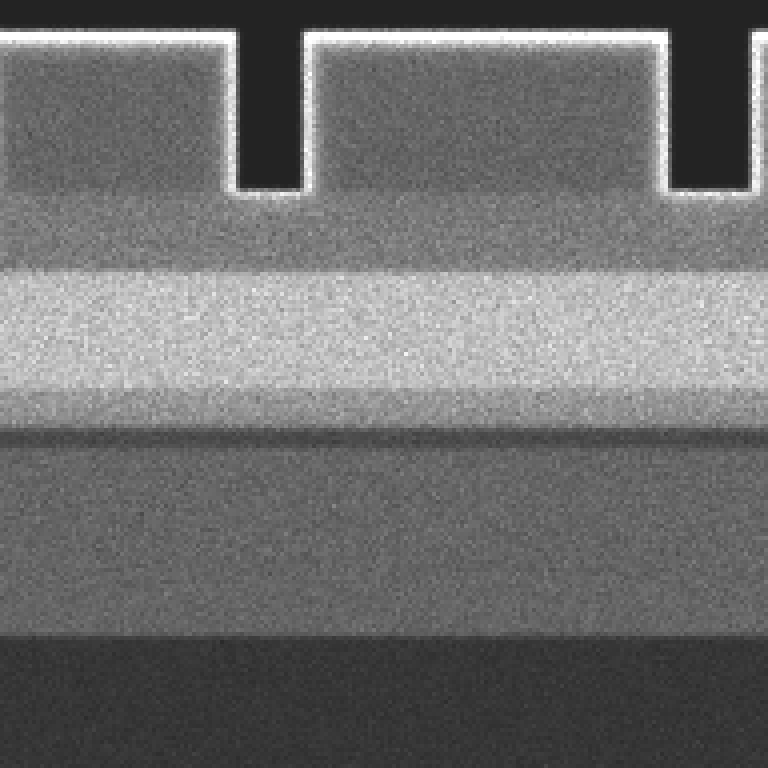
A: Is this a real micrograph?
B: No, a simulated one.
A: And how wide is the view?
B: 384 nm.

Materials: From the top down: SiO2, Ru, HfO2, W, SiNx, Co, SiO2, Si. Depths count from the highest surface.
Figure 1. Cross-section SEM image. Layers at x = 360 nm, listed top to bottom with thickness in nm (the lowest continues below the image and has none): empty 80, Ru 40, HfO2 58, W 20, SiNx 10, Co 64, SiO2 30, Si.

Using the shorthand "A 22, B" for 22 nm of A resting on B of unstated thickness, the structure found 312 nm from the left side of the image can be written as SiO2 80, Ru 40, HfO2 58, W 20, SiNx 10, Co 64, SiO2 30, Si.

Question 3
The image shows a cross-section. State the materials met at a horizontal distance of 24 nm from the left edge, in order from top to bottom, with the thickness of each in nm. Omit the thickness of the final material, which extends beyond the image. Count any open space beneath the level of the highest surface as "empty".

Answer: SiO2 80, Ru 40, HfO2 58, W 20, SiNx 10, Co 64, SiO2 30, Si